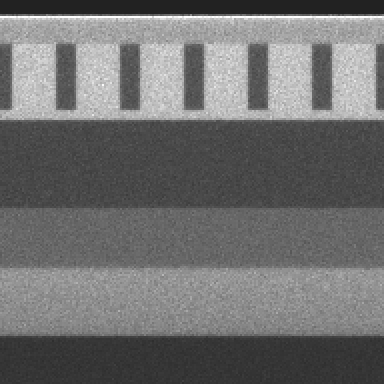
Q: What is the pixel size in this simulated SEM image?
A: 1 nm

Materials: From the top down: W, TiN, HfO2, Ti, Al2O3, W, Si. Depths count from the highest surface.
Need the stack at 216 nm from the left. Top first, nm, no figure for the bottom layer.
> W 28, HfO2 76, Ti 88, Al2O3 60, W 68, Si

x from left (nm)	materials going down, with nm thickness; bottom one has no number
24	W 28, HfO2 76, Ti 88, Al2O3 60, W 68, Si